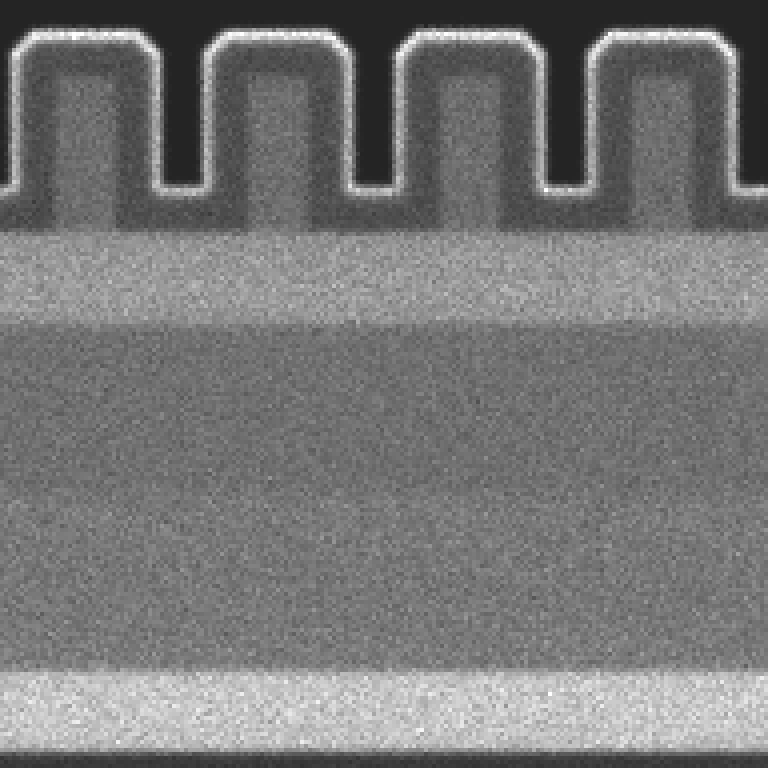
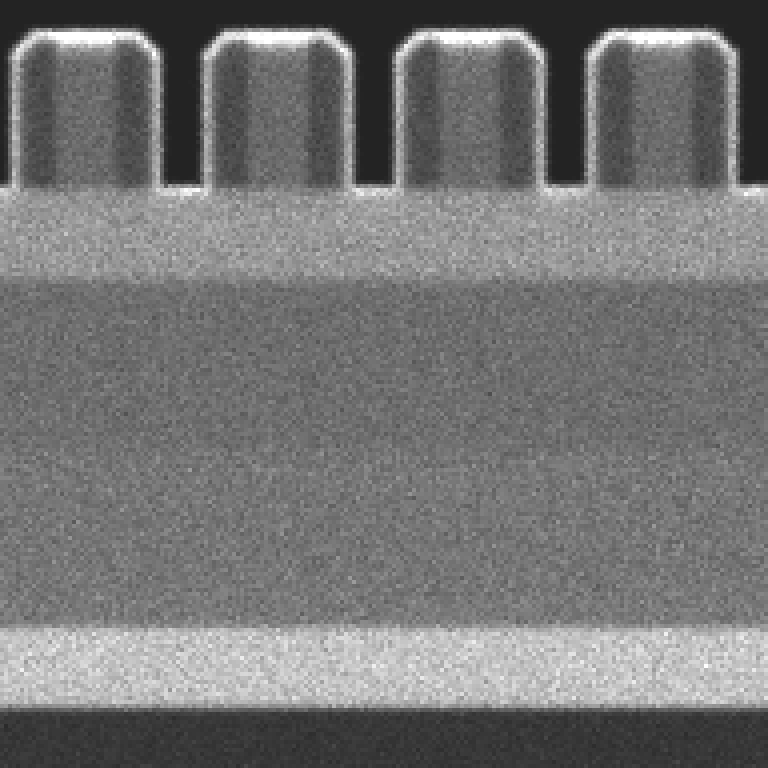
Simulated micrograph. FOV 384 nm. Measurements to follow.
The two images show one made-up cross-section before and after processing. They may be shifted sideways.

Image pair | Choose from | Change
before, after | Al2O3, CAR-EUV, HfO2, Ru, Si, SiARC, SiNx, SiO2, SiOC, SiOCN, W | SiNx (removed)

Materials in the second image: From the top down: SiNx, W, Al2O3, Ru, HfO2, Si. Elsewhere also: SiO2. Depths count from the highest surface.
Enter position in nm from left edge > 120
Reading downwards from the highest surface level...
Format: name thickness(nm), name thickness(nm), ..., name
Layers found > SiNx 78, W 46, Al2O3 84, Ru 90, HfO2 40, Si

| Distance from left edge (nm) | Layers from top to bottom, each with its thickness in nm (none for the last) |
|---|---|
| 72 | empty 4, SiNx 74, W 46, Al2O3 84, Ru 90, HfO2 40, Si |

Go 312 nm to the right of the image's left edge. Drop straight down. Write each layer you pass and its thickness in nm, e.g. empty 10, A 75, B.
SiNx 78, W 46, Al2O3 84, Ru 90, HfO2 40, Si